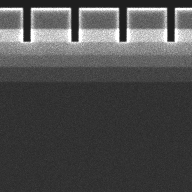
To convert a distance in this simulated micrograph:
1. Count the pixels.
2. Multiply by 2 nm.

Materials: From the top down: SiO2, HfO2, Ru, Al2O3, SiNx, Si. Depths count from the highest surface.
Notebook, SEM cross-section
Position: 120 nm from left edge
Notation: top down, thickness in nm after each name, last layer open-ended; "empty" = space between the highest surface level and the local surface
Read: SiO2 42, HfO2 26, Ru 26, Al2O3 24, SiNx 30, Si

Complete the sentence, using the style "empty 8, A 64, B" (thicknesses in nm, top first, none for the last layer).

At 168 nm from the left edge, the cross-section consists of SiO2 42, HfO2 26, Ru 26, Al2O3 24, SiNx 30, Si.